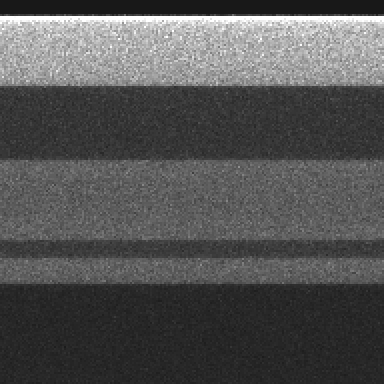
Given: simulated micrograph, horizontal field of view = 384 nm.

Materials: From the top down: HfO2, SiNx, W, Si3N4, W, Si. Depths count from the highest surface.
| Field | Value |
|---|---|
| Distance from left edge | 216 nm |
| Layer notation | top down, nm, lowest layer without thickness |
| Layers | HfO2 70, SiNx 74, W 80, Si3N4 18, W 26, Si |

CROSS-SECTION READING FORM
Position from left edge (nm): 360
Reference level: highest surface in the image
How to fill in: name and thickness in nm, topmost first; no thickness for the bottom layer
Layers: HfO2 70, SiNx 74, W 80, Si3N4 18, W 26, Si